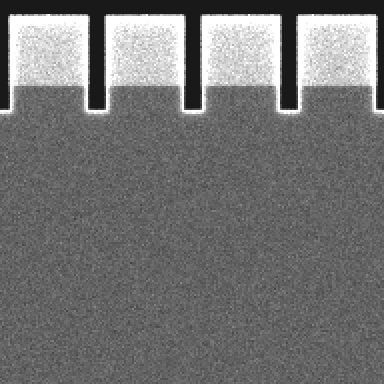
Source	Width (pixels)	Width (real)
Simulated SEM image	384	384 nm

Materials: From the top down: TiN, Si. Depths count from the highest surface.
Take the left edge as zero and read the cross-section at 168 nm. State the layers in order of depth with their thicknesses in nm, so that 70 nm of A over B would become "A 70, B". TiN 70, Si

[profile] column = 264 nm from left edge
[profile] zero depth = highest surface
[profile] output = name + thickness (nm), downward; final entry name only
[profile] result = TiN 70, Si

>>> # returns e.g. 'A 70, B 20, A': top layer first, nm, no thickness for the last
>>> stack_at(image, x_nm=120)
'TiN 70, Si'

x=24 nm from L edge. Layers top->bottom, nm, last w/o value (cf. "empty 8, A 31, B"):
TiN 70, Si